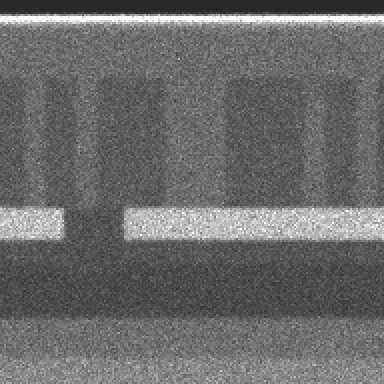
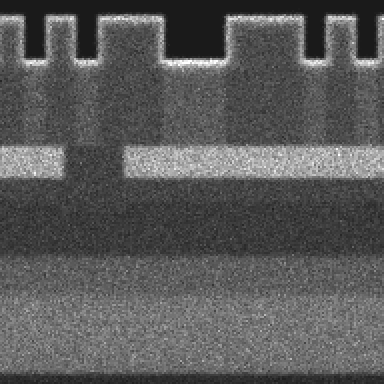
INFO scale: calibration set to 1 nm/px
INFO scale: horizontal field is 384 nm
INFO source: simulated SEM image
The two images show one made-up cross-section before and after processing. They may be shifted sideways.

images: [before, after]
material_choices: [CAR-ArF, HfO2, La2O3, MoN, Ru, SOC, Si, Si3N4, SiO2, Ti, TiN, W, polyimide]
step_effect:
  removed: SiO2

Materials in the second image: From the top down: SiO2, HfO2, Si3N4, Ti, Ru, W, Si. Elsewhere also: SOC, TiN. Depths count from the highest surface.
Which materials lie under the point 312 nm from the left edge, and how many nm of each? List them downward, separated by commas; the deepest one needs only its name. empty 44, SiO2 86, HfO2 32, Si3N4 24, Ti 54, Ru 40, W 78, Si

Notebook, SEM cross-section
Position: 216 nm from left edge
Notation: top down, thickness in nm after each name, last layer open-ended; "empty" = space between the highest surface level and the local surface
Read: empty 44, SiO2 86, HfO2 32, Si3N4 24, Ti 54, Ru 40, W 78, Si